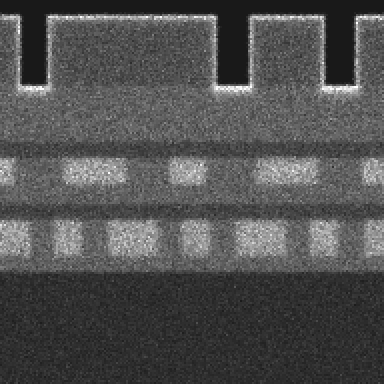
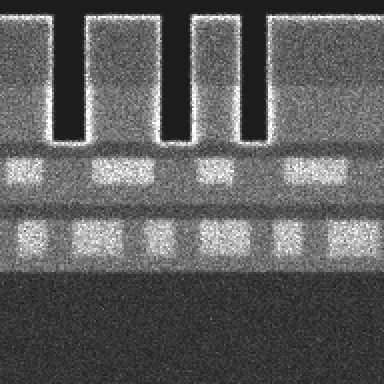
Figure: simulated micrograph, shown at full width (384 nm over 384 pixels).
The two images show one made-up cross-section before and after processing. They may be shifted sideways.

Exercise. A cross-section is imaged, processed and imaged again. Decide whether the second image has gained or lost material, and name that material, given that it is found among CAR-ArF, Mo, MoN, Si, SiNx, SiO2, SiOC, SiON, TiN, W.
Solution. removed: SiO2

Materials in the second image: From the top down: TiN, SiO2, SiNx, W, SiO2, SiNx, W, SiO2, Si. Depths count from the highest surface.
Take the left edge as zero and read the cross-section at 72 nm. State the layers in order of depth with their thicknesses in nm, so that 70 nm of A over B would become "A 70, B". empty 126, SiNx 16, SiO2 46, SiNx 16, W 36, SiO2 16, Si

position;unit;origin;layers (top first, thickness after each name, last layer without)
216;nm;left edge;TiN 70, SiO2 56, SiNx 16, W 26, SiO2 20, SiNx 16, W 36, SiO2 16, Si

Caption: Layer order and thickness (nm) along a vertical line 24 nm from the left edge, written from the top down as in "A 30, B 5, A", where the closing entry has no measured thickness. TiN 70, SiO2 56, SiNx 16, W 26, SiO2 20, SiNx 16, W 36, SiO2 16, Si